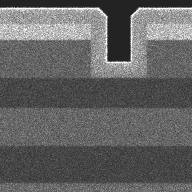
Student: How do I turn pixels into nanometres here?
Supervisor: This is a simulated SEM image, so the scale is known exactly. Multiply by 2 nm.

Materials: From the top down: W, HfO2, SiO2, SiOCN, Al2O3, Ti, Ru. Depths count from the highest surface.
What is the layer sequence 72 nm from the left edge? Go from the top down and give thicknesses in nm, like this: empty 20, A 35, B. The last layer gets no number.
W 32, HfO2 32, SiO2 76, SiOCN 60, Al2O3 76, Ti 74, Ru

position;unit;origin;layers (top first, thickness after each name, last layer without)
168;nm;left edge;W 32, HfO2 32, SiO2 76, SiOCN 60, Al2O3 76, Ti 74, Ru